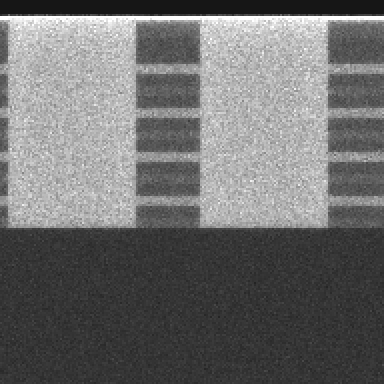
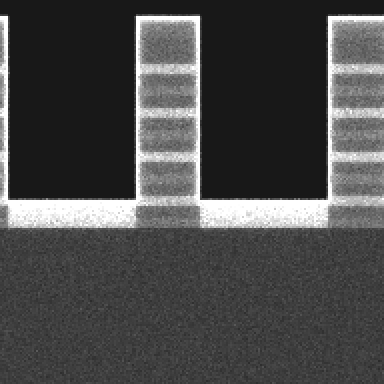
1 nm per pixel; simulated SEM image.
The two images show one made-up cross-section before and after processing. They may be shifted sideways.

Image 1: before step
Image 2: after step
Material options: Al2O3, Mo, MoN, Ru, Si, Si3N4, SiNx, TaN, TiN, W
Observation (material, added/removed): W, removed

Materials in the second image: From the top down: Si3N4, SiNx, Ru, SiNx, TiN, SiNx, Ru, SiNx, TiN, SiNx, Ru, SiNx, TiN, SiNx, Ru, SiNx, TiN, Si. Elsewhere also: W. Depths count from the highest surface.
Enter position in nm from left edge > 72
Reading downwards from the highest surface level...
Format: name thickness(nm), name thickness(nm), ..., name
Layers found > empty 184, W 28, Si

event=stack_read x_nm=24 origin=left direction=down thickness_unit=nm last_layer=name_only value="empty 184, W 28, Si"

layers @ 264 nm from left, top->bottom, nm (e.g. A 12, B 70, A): empty 184, W 28, Si